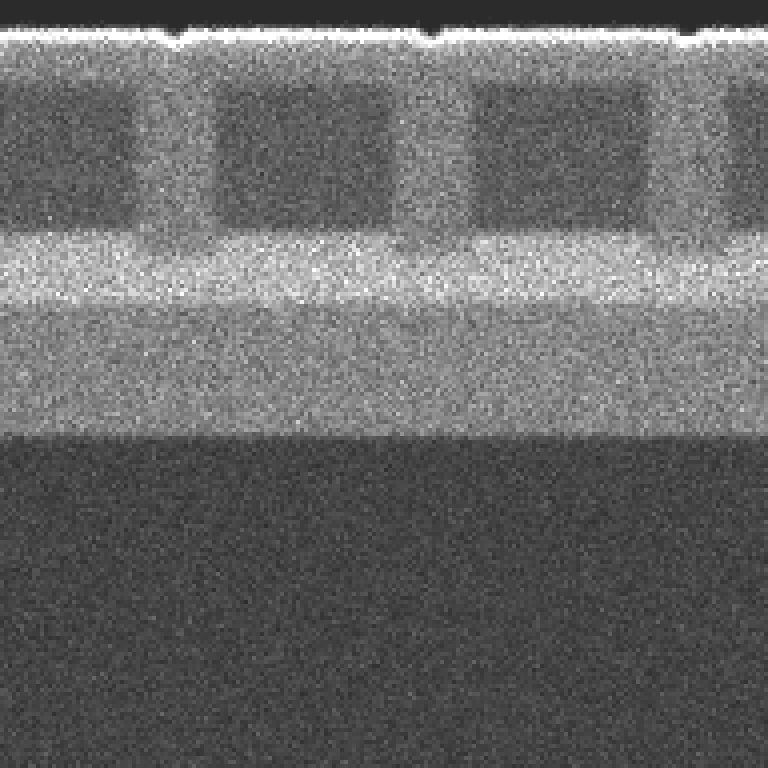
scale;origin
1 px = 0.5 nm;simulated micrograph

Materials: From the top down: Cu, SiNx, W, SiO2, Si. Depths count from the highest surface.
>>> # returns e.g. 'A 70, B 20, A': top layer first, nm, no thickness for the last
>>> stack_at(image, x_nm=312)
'Cu 26, SiNx 74, W 36, SiO2 66, Si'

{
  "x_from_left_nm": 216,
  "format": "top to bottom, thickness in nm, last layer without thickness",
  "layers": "empty 4, Cu 108, W 24, SiO2 66, Si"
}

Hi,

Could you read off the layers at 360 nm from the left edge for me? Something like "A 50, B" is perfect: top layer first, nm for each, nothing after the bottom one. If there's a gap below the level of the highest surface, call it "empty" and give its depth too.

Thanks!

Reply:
Cu 112, W 24, SiO2 66, Si